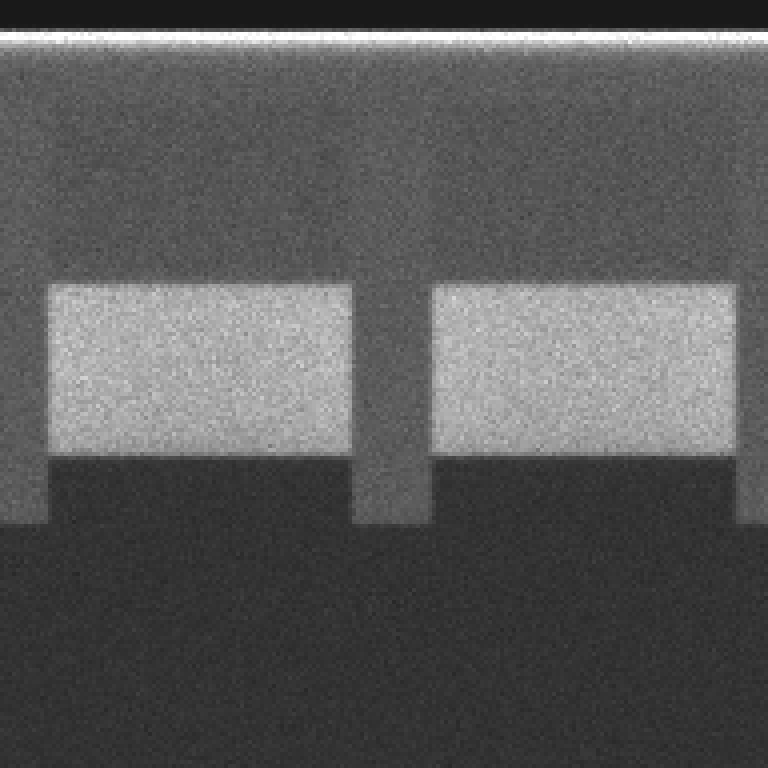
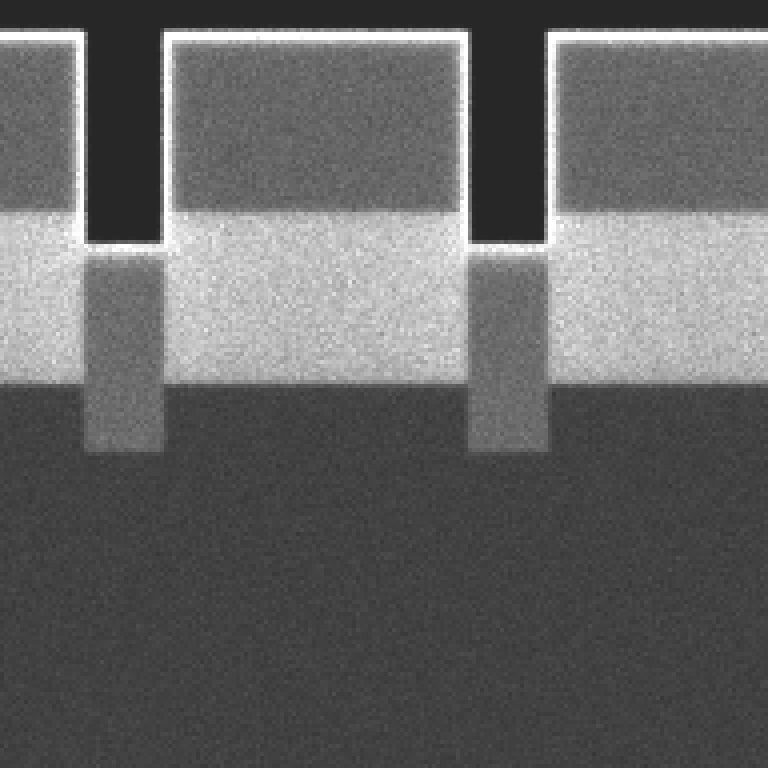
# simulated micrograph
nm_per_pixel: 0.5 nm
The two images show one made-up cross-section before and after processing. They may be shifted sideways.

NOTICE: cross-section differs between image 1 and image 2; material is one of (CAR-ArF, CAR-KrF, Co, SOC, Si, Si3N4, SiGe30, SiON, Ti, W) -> removed: SOC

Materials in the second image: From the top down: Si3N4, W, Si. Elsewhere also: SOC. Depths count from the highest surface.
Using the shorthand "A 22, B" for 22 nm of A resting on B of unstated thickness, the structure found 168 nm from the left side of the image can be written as Si3N4 90, W 86, Si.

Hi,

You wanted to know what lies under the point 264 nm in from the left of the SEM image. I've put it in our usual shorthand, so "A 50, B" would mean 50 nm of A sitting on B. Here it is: empty 106, SOC 104, Si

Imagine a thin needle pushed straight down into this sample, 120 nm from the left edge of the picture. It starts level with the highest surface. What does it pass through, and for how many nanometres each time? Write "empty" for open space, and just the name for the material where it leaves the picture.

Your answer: Si3N4 90, W 86, Si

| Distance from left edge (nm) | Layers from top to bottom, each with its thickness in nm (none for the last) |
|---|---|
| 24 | Si3N4 90, W 86, Si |